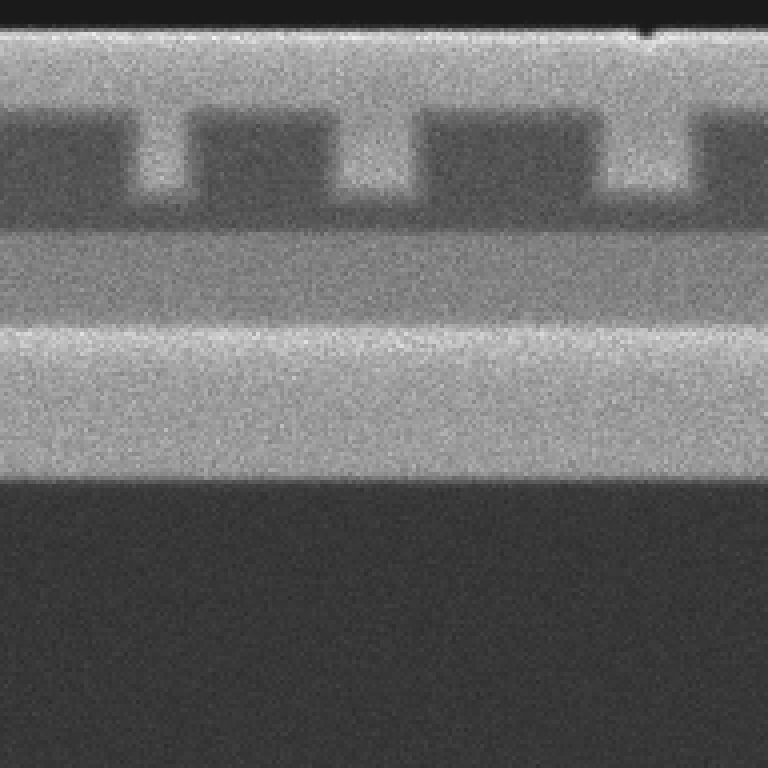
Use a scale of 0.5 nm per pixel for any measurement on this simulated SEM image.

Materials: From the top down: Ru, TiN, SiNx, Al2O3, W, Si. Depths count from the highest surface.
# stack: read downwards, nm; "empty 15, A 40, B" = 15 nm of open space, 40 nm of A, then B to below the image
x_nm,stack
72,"Ru 78, TiN 8, SiNx 14, Al2O3 48, W 76, Si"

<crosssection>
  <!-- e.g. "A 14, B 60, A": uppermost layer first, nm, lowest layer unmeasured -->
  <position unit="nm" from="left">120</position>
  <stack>Ru 38, TiN 8, SiNx 54, Al2O3 48, W 76, Si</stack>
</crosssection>